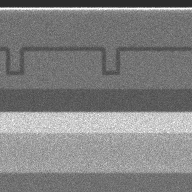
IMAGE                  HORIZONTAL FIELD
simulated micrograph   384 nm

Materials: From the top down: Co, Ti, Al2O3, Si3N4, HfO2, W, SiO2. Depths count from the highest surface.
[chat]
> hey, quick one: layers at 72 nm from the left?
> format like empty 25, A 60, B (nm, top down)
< Co 78, Ti 8, Al2O3 76, Si3N4 46, HfO2 42, W 80, SiO2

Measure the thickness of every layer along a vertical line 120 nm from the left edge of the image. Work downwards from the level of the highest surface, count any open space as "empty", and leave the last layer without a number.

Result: Co 78, Ti 8, Al2O3 76, Si3N4 46, HfO2 42, W 80, SiO2